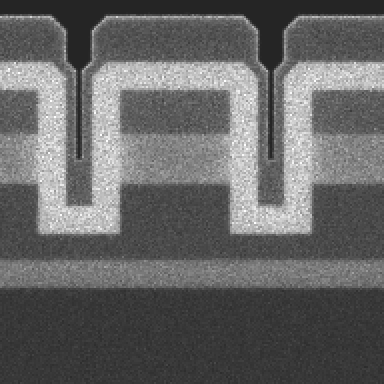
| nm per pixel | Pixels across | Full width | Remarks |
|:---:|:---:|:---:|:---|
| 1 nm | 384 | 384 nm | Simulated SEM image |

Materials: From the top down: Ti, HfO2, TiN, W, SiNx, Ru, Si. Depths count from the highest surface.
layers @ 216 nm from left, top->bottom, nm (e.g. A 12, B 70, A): Ti 46, HfO2 28, TiN 44, W 50, SiNx 76, Ru 28, Si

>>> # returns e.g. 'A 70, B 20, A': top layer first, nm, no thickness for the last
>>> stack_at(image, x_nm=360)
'Ti 46, HfO2 28, TiN 44, W 50, SiNx 76, Ru 28, Si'